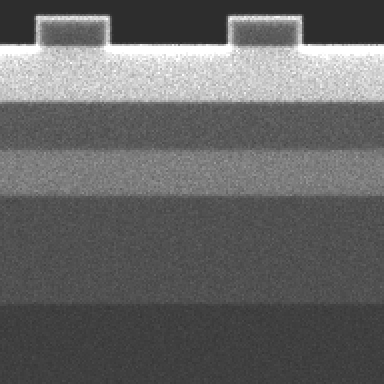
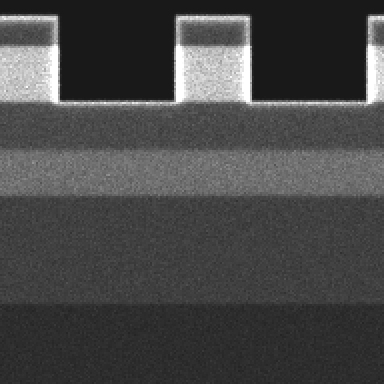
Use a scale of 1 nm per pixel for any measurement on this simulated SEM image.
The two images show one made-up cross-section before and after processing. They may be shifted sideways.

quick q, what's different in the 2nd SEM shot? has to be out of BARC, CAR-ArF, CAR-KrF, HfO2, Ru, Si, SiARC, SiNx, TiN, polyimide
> HfO2 removed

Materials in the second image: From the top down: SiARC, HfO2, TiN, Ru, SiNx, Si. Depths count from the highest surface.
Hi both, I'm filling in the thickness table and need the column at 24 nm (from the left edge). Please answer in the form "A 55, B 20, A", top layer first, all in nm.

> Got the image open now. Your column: SiARC 30, HfO2 56, TiN 48, Ru 46, SiNx 108, Si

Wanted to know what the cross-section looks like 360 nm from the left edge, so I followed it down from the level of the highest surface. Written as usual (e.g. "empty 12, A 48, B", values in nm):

empty 86, TiN 48, Ru 46, SiNx 108, Si